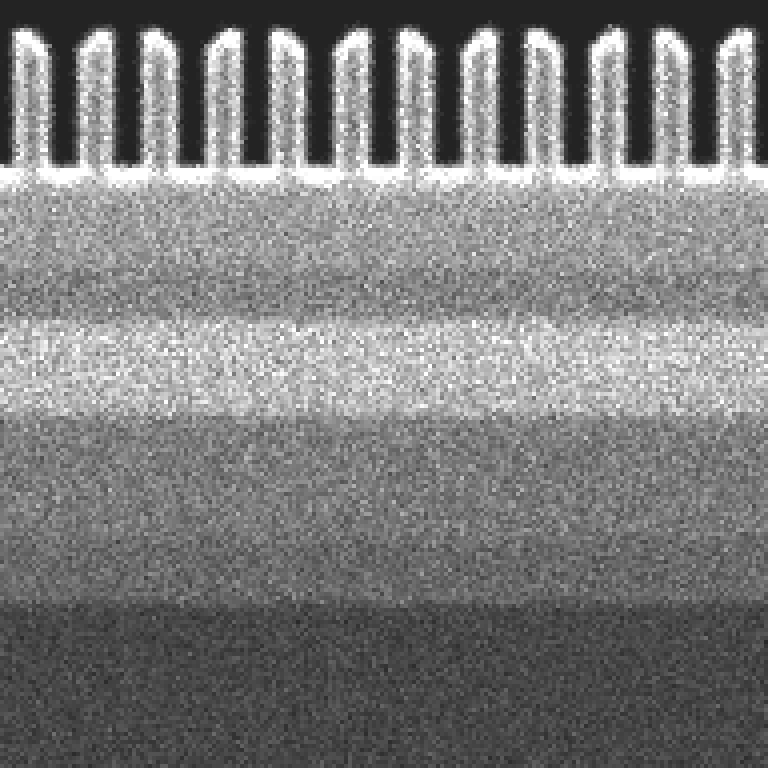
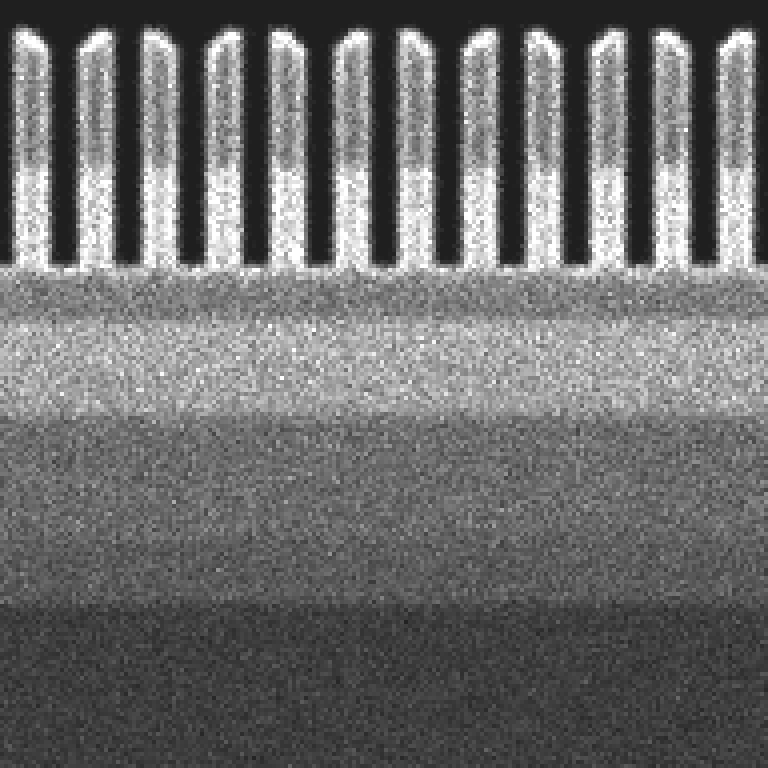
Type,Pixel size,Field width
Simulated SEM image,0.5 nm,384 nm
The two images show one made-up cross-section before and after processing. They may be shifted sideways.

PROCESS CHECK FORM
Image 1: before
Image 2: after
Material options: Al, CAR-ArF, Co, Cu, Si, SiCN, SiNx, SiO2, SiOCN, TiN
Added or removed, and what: removed, SiO2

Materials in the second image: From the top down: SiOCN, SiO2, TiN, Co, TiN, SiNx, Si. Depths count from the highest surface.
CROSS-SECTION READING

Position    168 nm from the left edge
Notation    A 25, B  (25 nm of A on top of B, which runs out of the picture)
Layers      empty 8, SiOCN 60, SiO2 50, TiN 26, Co 48, TiN 62, SiNx 32, Si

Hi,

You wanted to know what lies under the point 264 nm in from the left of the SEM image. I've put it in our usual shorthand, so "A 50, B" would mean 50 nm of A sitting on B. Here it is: SiOCN 68, SiO2 50, TiN 26, Co 48, TiN 62, SiNx 32, Si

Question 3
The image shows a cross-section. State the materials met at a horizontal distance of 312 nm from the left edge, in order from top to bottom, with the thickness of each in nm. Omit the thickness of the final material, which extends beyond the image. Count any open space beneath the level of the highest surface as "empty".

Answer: empty 118, TiN 26, Co 48, TiN 62, SiNx 32, Si